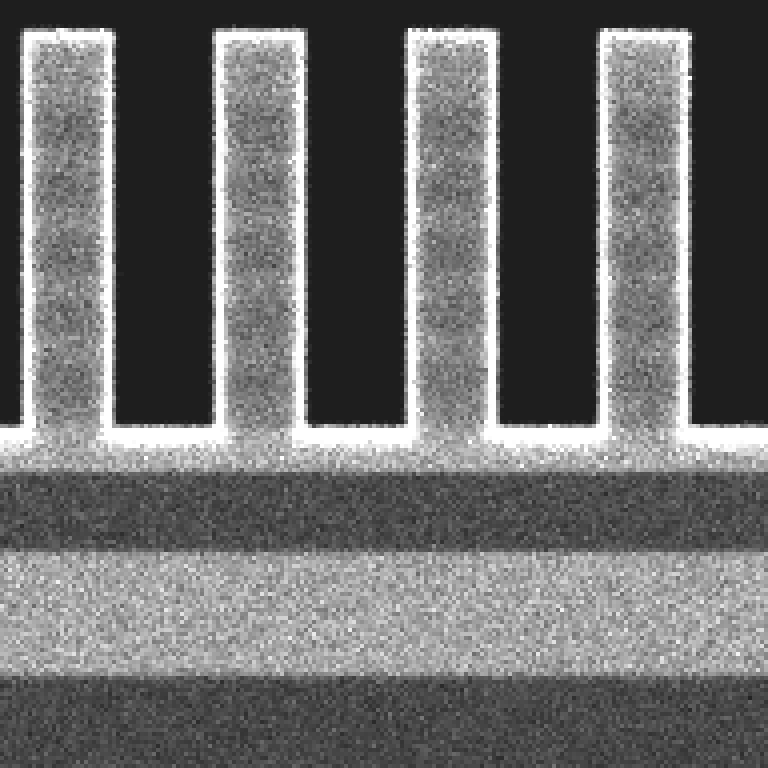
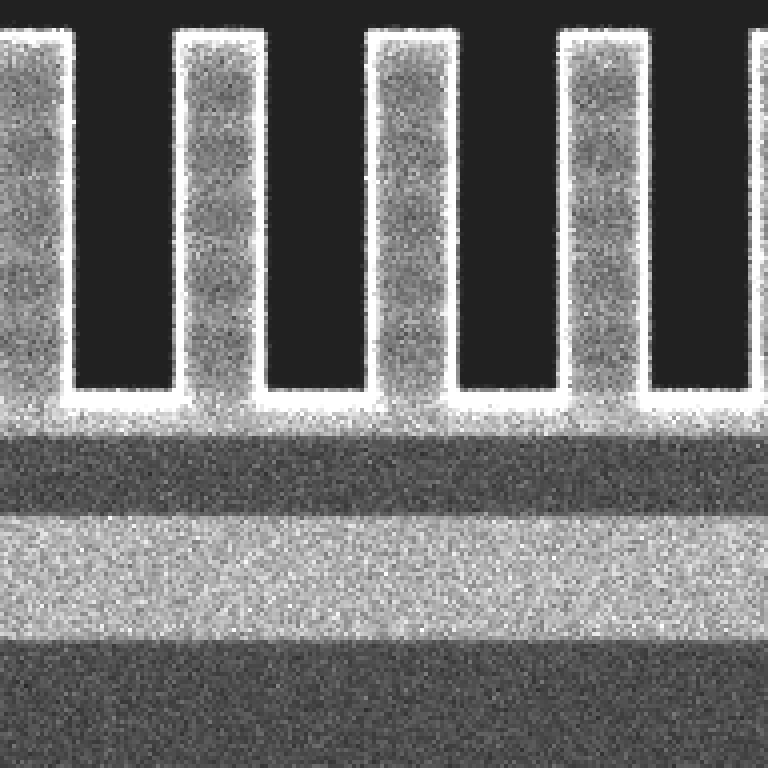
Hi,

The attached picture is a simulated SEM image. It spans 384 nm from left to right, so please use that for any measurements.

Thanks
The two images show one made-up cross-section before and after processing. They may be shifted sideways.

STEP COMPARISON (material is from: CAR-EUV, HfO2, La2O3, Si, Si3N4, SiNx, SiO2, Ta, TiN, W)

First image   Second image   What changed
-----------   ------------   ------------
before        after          TiN, removed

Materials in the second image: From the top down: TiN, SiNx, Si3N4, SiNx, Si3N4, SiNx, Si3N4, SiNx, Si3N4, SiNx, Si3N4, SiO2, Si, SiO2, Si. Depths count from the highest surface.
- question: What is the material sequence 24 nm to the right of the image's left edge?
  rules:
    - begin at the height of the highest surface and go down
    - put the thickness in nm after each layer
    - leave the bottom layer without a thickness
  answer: TiN 20, SiNx 18, Si3N4 14, SiNx 18, Si3N4 14, SiNx 18, Si3N4 14, SiNx 18, Si3N4 14, SiNx 18, Si3N4 14, SiO2 22, Si 40, SiO2 62, Si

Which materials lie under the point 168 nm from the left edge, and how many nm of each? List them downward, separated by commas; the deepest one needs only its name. empty 180, SiO2 22, Si 40, SiO2 62, Si